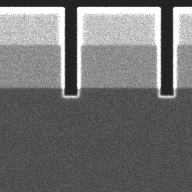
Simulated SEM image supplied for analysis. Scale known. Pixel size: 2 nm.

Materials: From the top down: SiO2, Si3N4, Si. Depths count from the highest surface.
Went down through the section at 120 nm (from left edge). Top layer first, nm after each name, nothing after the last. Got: SiO2 74, Si3N4 86, Si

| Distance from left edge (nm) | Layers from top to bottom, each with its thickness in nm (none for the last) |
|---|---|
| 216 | SiO2 74, Si3N4 86, Si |